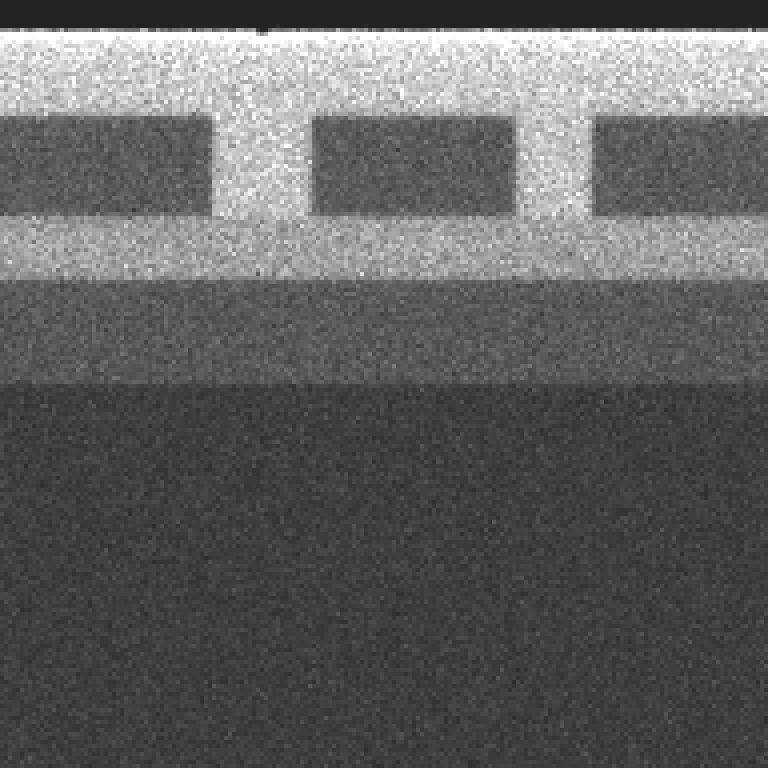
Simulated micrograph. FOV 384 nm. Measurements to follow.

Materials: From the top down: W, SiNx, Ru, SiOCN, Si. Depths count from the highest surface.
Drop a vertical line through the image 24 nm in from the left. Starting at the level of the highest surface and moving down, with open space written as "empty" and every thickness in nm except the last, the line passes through W 42, SiNx 50, Ru 32, SiOCN 52, Si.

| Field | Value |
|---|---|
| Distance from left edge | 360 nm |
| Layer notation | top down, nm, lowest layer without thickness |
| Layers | W 42, SiNx 50, Ru 32, SiOCN 52, Si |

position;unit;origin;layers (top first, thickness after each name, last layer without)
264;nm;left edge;W 92, Ru 32, SiOCN 52, Si